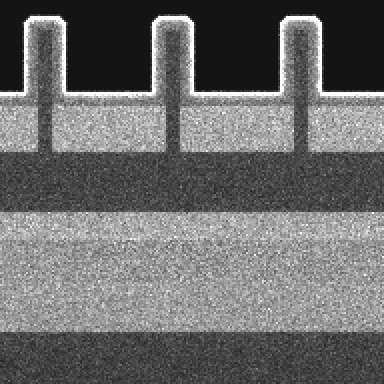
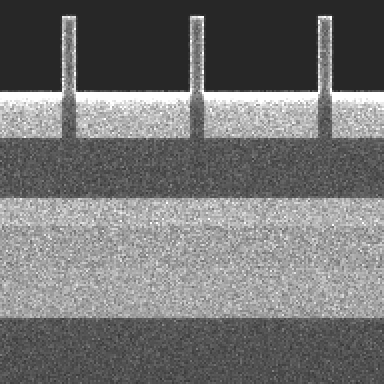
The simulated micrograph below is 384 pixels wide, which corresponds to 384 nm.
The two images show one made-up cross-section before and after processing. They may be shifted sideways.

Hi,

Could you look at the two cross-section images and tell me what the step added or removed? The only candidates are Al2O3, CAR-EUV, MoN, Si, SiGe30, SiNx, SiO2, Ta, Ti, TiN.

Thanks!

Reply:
removed SiNx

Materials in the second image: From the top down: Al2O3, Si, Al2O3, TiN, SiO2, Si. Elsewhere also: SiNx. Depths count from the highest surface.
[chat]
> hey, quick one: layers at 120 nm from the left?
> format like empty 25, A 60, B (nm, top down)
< empty 76, Al2O3 46, Si 60, Al2O3 28, TiN 42, SiO2 50, Si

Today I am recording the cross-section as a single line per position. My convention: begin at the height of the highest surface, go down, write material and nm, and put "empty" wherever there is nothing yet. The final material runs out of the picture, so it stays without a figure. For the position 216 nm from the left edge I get empty 76, Al2O3 46, Si 60, Al2O3 28, TiN 42, SiO2 50, Si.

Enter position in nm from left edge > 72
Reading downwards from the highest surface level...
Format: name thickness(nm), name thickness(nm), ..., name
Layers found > Si 182, Al2O3 28, TiN 42, SiO2 50, Si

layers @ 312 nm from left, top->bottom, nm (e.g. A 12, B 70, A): empty 76, Al2O3 46, Si 60, Al2O3 28, TiN 42, SiO2 50, Si